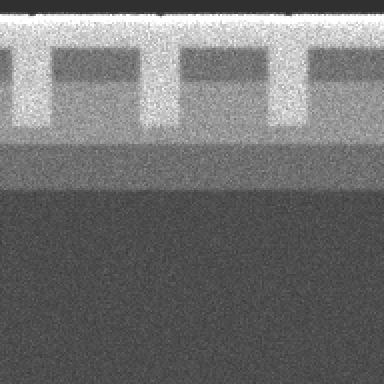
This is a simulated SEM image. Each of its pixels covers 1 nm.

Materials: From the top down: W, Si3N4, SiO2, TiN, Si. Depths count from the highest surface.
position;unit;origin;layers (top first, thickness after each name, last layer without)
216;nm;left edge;W 32, Si3N4 34, SiO2 62, TiN 46, Si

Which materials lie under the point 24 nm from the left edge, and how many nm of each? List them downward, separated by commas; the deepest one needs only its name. W 110, SiO2 18, TiN 46, Si